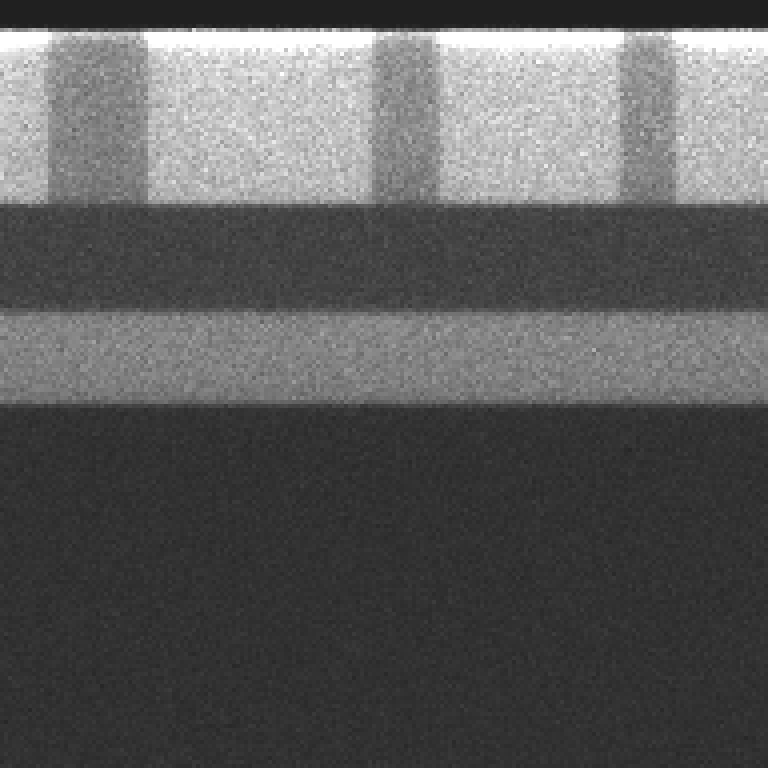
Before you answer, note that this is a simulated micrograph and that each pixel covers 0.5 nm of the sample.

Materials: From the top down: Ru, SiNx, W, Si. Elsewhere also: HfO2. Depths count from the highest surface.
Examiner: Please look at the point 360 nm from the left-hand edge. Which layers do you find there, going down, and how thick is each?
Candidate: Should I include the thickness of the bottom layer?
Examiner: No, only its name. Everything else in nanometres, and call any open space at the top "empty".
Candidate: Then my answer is HfO2 86, SiNx 54, W 46, Si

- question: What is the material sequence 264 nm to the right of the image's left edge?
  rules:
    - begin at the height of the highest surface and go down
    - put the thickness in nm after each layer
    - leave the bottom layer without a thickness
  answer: HfO2 86, SiNx 54, W 46, Si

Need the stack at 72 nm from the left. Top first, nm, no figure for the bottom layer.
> Ru 86, SiNx 54, W 46, Si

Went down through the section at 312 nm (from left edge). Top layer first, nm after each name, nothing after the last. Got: Ru 86, SiNx 54, W 46, Si